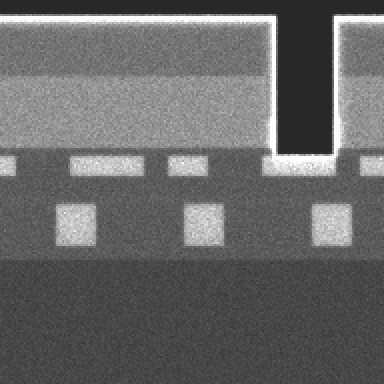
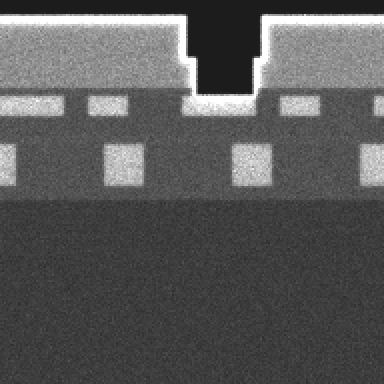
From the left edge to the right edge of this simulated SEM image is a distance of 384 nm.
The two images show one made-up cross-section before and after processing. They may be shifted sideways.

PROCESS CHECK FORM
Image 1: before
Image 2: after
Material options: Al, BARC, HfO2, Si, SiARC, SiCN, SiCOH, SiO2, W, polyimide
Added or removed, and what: removed, SiARC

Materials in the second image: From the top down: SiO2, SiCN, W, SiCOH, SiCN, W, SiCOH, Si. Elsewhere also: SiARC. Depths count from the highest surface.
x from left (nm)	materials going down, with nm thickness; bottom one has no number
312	SiO2 72, SiCN 8, W 20, SiCOH 20, SiCN 8, SiCOH 56, Si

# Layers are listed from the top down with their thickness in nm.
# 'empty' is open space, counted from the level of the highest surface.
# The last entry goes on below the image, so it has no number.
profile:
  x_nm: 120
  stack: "SiO2 72, SiCN 8, W 20, SiCOH 20, SiCN 8, W 42, SiCOH 14, Si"